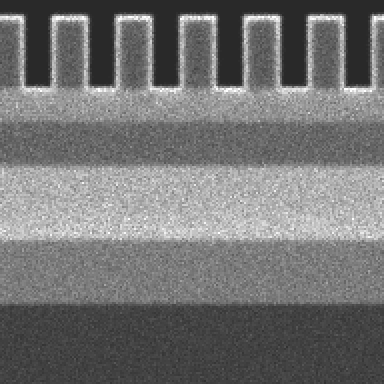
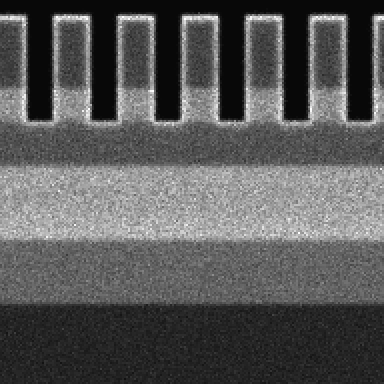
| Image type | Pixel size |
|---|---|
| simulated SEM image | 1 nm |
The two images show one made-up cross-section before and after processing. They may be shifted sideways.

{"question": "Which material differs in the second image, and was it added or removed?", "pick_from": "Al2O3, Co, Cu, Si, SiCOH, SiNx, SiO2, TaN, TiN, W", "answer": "Co, removed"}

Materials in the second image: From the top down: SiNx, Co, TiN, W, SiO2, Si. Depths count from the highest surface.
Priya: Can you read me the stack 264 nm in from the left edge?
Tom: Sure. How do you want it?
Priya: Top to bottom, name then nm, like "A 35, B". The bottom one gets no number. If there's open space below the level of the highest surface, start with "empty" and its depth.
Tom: SiNx 72, Co 34, TiN 44, W 74, SiO2 64, Si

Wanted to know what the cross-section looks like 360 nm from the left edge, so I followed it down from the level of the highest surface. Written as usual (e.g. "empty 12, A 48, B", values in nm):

empty 106, TiN 44, W 74, SiO2 64, Si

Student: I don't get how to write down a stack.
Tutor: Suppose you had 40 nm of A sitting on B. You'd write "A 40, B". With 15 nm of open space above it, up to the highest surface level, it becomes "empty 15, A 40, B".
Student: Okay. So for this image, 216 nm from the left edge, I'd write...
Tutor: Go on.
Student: SiNx 72, Co 34, TiN 44, W 74, SiO2 64, Si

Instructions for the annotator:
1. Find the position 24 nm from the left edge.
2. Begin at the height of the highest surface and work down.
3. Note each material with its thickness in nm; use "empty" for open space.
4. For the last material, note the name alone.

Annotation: SiNx 72, Co 34, TiN 44, W 74, SiO2 64, Si